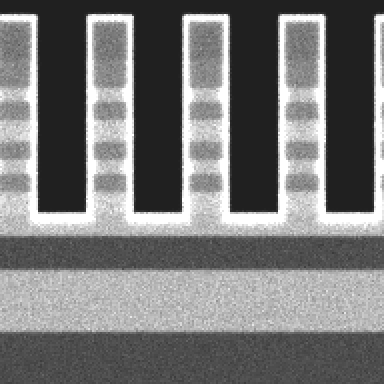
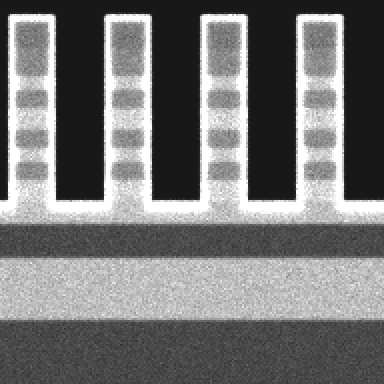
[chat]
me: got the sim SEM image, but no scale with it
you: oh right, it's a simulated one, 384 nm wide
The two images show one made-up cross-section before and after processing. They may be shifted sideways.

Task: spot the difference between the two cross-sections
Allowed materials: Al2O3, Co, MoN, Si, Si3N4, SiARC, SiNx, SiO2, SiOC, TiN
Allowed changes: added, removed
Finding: removed SiNx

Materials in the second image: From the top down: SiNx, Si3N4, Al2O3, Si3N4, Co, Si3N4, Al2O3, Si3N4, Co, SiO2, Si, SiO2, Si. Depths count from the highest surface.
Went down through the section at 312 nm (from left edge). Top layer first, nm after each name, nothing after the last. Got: SiNx 32, Si3N4 28, Al2O3 14, Si3N4 18, Co 22, Si3N4 18, Al2O3 14, Si3N4 18, Co 22, SiO2 22, Si 34, SiO2 62, Si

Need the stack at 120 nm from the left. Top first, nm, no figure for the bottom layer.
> SiNx 32, Si3N4 28, Al2O3 14, Si3N4 18, Co 22, Si3N4 18, Al2O3 14, Si3N4 18, Co 22, SiO2 22, Si 34, SiO2 62, Si